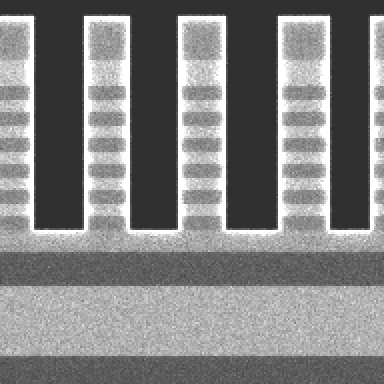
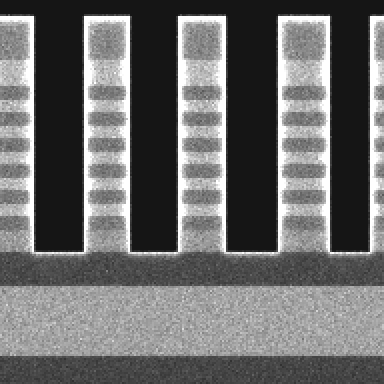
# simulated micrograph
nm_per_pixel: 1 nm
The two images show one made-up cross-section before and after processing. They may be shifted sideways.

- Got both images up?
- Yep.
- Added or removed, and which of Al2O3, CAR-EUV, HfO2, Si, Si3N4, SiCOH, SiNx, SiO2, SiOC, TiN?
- removed, TiN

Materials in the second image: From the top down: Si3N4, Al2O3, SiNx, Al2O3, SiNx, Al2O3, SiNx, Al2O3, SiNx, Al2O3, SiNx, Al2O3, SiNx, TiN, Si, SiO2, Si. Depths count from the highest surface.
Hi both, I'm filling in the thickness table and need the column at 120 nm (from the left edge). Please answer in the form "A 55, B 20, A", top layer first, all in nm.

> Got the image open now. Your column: Si3N4 44, Al2O3 26, SiNx 14, Al2O3 12, SiNx 14, Al2O3 12, SiNx 14, Al2O3 12, SiNx 14, Al2O3 12, SiNx 14, Al2O3 12, SiNx 14, TiN 22, Si 34, SiO2 70, Si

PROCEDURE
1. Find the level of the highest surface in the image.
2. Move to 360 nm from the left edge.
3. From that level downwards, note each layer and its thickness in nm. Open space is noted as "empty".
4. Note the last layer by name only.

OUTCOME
empty 236, Si 34, SiO2 70, Si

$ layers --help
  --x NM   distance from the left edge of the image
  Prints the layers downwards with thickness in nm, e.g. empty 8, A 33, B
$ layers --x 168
empty 236, Si 34, SiO2 70, Si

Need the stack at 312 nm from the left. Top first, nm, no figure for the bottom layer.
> Si3N4 44, Al2O3 26, SiNx 14, Al2O3 12, SiNx 14, Al2O3 12, SiNx 14, Al2O3 12, SiNx 14, Al2O3 12, SiNx 14, Al2O3 12, SiNx 14, TiN 22, Si 34, SiO2 70, Si